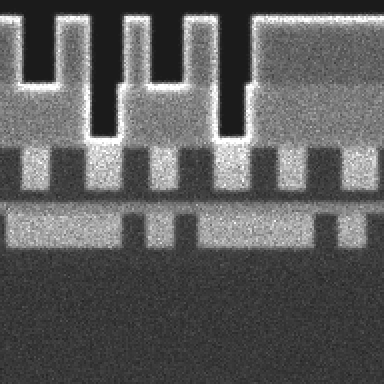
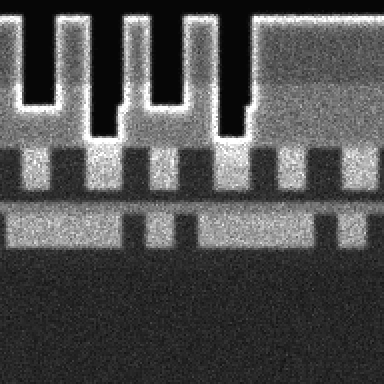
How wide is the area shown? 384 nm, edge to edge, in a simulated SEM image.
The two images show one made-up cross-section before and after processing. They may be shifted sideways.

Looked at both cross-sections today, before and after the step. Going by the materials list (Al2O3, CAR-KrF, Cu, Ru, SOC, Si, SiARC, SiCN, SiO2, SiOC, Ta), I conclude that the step removed SiO2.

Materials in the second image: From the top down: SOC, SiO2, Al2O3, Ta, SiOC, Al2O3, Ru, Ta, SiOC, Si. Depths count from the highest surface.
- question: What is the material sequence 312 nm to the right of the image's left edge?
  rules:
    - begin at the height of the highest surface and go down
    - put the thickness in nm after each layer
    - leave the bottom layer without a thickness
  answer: SOC 68, SiO2 54, Al2O3 10, SiOC 54, Al2O3 12, Ta 34, SiOC 20, Si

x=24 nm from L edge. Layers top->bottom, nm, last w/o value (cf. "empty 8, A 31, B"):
empty 90, SiO2 32, Al2O3 10, Ta 42, SiOC 12, Al2O3 12, Ru 26, Ta 8, SiOC 20, Si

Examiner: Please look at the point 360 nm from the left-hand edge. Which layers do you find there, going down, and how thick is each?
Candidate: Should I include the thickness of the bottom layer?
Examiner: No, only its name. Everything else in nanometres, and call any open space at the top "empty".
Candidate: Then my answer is SOC 68, SiO2 54, Al2O3 10, Ru 34, Ta 8, SiOC 12, Al2O3 12, Ta 34, SiOC 20, Si